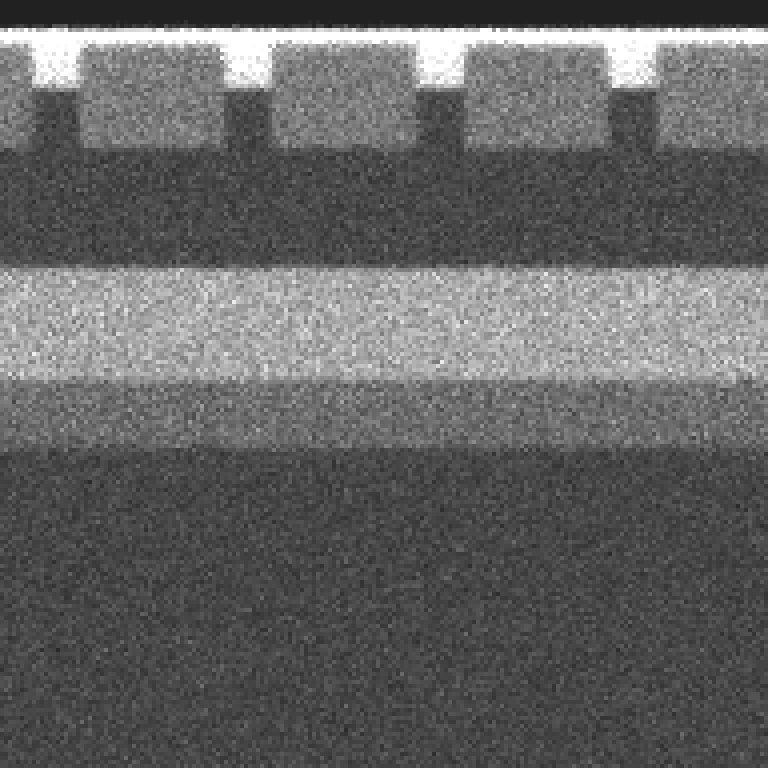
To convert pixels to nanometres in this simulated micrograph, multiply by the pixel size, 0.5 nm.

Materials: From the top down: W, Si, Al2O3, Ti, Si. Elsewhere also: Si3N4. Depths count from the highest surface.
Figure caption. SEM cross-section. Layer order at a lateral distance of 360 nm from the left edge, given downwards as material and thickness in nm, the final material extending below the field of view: Si3N4 58, Si 60, Al2O3 56, Ti 34, Si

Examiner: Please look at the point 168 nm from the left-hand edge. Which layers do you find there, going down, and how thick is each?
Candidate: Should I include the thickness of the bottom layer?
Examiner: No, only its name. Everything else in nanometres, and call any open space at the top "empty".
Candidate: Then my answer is Si3N4 58, Si 60, Al2O3 56, Ti 34, Si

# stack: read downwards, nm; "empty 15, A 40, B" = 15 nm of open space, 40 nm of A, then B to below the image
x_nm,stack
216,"W 28, Si 90, Al2O3 56, Ti 34, Si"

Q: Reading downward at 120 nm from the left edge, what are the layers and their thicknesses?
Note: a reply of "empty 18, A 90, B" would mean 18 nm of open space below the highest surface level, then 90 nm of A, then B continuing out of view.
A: W 28, Si 90, Al2O3 56, Ti 34, Si